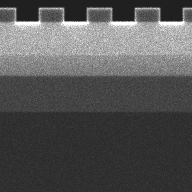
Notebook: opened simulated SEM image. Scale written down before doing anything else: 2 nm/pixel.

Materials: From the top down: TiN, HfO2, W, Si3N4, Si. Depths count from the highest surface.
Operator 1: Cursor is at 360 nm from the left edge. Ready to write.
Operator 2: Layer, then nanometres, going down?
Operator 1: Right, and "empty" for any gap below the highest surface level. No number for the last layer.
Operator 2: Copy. empty 28, HfO2 66, W 42, Si3N4 72, Si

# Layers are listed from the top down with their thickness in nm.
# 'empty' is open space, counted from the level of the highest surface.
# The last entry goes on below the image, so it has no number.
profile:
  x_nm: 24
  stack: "TiN 28, HfO2 66, W 42, Si3N4 72, Si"